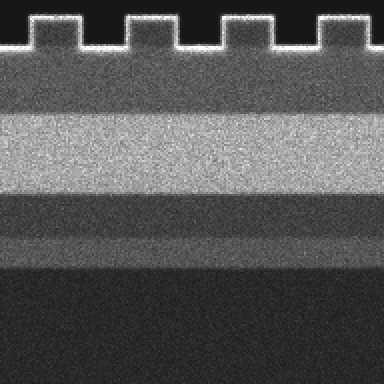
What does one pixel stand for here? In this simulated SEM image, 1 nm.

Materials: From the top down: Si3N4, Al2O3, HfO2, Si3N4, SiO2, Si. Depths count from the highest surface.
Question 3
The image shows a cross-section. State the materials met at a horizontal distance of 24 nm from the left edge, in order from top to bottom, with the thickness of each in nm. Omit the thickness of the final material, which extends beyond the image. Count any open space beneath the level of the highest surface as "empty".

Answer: empty 30, Al2O3 68, HfO2 80, Si3N4 44, SiO2 30, Si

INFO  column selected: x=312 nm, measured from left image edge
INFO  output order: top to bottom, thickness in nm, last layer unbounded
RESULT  empty 30, Al2O3 68, HfO2 80, Si3N4 44, SiO2 30, Si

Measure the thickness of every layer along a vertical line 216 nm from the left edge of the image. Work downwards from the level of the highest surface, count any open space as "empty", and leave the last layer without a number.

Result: empty 30, Al2O3 68, HfO2 80, Si3N4 44, SiO2 30, Si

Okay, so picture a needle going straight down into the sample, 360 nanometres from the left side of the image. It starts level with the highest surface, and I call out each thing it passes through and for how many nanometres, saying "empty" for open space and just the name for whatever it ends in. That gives Si3N4 30, Al2O3 68, HfO2 80, Si3N4 44, SiO2 30, Si